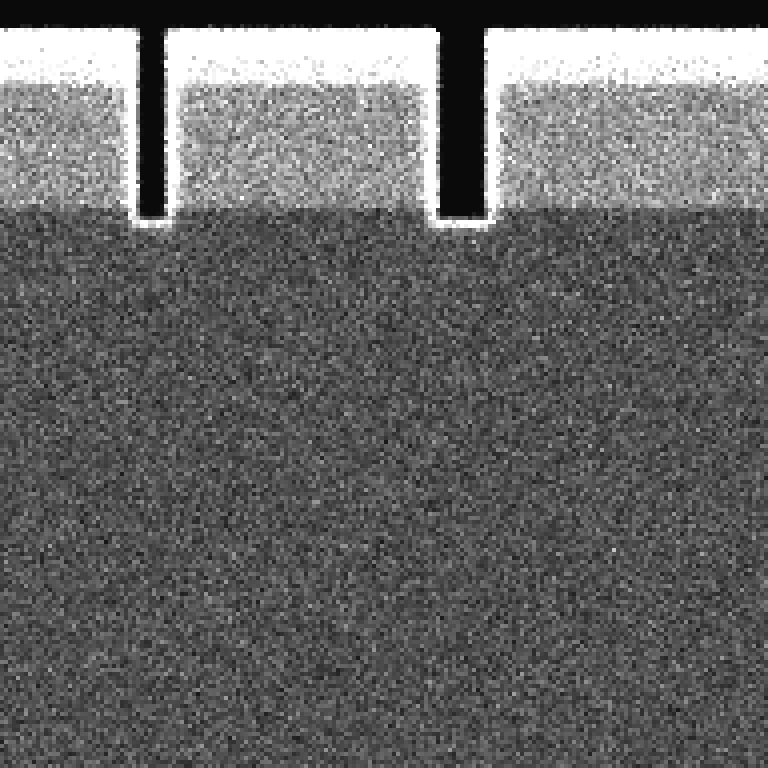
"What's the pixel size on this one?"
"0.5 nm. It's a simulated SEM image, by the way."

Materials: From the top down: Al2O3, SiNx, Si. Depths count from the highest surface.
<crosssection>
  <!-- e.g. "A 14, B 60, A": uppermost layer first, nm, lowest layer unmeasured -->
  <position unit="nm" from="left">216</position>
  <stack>Al2O3 26, SiNx 62, Si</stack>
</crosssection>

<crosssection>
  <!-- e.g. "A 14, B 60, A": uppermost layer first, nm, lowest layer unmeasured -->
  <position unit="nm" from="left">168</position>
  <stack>Al2O3 26, SiNx 62, Si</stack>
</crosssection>